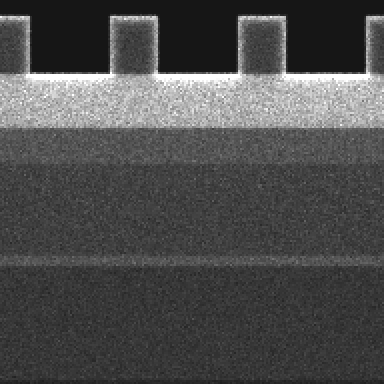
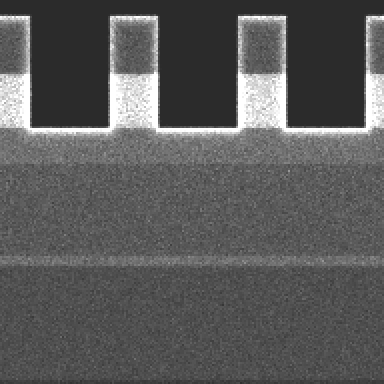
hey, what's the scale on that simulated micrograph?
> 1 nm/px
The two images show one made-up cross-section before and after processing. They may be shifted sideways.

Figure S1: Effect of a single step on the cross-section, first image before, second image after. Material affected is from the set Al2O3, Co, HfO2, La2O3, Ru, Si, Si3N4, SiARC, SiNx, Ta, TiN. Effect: removed HfO2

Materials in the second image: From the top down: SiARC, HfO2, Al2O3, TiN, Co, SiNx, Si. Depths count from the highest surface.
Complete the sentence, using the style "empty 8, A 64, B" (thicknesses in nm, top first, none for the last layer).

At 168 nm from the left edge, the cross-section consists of empty 112, Al2O3 36, TiN 92, Co 10, SiNx 114, Si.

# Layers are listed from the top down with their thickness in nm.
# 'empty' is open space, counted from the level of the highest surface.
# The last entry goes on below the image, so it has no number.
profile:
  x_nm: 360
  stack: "empty 112, Al2O3 36, TiN 92, Co 10, SiNx 114, Si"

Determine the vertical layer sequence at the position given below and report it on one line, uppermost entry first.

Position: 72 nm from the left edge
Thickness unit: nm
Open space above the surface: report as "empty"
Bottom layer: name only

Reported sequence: empty 112, Al2O3 36, TiN 92, Co 10, SiNx 114, Si